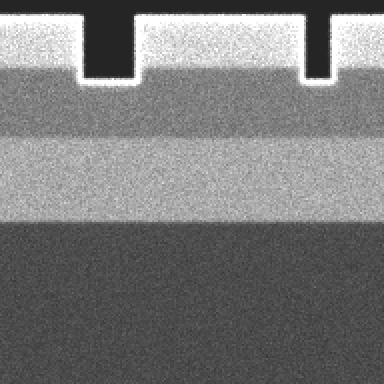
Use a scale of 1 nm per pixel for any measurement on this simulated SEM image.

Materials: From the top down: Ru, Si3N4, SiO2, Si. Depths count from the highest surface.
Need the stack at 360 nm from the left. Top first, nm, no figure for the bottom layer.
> Ru 52, Si3N4 70, SiO2 84, Si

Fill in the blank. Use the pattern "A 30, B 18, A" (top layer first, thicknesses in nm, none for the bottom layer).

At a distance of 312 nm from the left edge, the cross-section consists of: empty 64, Si3N4 58, SiO2 84, Si